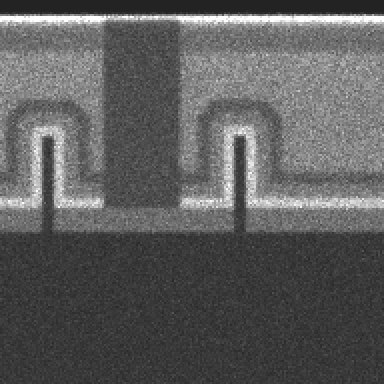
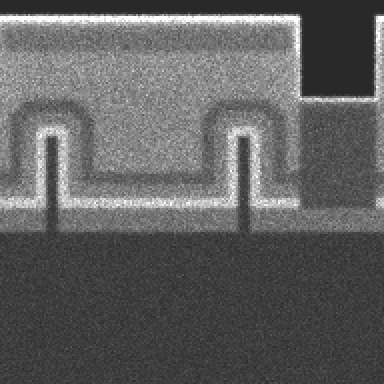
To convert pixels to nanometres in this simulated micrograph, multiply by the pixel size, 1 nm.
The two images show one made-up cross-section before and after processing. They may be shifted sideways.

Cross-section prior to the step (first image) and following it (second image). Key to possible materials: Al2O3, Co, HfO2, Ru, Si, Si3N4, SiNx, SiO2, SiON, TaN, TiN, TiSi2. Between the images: SiNx was removed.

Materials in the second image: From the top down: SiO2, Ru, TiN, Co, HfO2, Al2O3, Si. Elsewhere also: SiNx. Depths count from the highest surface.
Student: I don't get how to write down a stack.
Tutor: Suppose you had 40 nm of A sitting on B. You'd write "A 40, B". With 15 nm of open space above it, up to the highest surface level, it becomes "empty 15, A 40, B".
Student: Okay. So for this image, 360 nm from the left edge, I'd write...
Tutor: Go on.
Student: empty 82, SiNx 110, Al2O3 24, Si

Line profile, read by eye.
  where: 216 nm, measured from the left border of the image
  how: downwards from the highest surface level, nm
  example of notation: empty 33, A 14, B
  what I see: SiO2 36, Ru 50, TiN 18, Co 78, HfO2 10, Al2O3 24, Si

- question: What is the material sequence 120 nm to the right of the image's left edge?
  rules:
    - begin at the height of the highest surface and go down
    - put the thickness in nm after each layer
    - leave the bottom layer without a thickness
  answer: SiO2 36, Ru 120, TiN 12, Co 14, HfO2 10, Al2O3 24, Si